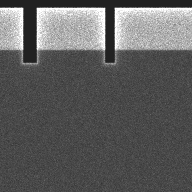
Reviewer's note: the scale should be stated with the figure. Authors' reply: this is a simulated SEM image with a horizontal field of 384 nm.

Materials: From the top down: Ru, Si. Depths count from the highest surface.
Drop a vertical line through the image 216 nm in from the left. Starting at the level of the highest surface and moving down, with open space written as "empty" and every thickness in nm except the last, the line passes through empty 110, Si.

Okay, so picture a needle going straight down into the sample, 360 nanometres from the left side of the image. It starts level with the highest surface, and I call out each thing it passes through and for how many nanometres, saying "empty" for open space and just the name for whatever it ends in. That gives Ru 84, Si